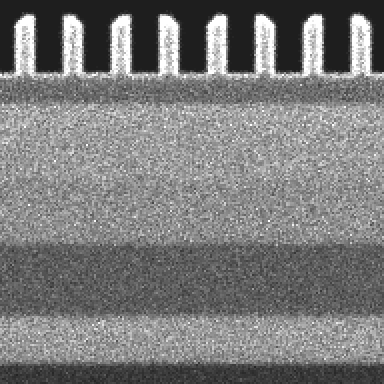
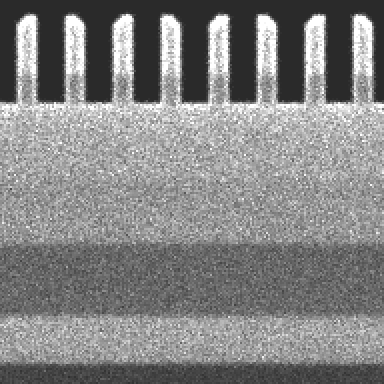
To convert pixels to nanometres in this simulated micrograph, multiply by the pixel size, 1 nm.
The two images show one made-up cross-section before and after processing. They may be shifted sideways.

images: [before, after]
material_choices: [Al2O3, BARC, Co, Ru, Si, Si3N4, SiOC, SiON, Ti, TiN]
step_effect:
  removed: TiN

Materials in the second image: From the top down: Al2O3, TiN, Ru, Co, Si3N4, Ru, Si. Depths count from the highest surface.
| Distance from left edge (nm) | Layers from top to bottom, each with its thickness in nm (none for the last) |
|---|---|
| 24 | empty 2, Al2O3 56, TiN 30, Ru 76, Co 64, Si3N4 72, Ru 48, Si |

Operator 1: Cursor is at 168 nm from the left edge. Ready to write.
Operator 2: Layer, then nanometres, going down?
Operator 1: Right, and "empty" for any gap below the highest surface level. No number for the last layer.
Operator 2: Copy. Al2O3 58, TiN 30, Ru 76, Co 64, Si3N4 72, Ru 48, Si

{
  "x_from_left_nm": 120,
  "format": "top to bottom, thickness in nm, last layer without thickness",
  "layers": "empty 2, Al2O3 56, TiN 30, Ru 76, Co 64, Si3N4 72, Ru 48, Si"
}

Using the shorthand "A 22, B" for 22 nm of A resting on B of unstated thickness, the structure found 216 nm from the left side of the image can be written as empty 2, Al2O3 56, TiN 30, Ru 76, Co 64, Si3N4 72, Ru 48, Si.